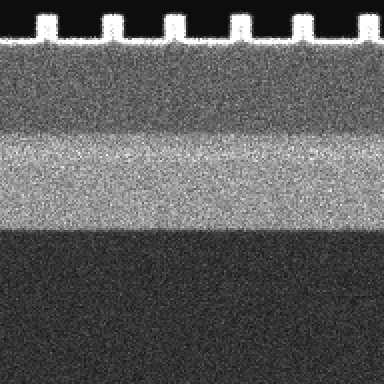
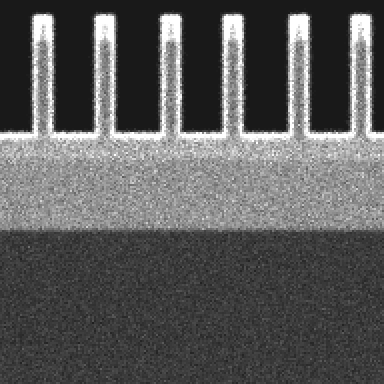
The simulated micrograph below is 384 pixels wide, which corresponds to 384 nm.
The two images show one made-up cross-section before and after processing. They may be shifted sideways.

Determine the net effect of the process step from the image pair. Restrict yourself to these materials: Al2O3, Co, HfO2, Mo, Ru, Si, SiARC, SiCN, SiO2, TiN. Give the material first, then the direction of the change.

TiN: removed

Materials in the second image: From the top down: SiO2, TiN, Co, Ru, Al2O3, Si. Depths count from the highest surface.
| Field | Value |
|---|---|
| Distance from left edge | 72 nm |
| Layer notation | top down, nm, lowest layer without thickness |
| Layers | empty 118, Co 14, Ru 12, Al2O3 70, Si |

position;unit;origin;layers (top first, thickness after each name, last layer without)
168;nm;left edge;SiO2 24, TiN 94, Co 14, Ru 12, Al2O3 70, Si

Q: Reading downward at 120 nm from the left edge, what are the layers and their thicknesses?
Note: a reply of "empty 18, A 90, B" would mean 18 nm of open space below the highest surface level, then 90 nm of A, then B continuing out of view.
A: empty 118, Co 14, Ru 12, Al2O3 70, Si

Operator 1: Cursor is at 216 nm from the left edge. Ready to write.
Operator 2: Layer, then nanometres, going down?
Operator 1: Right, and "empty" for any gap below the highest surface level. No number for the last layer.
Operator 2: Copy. empty 118, Co 14, Ru 12, Al2O3 70, Si